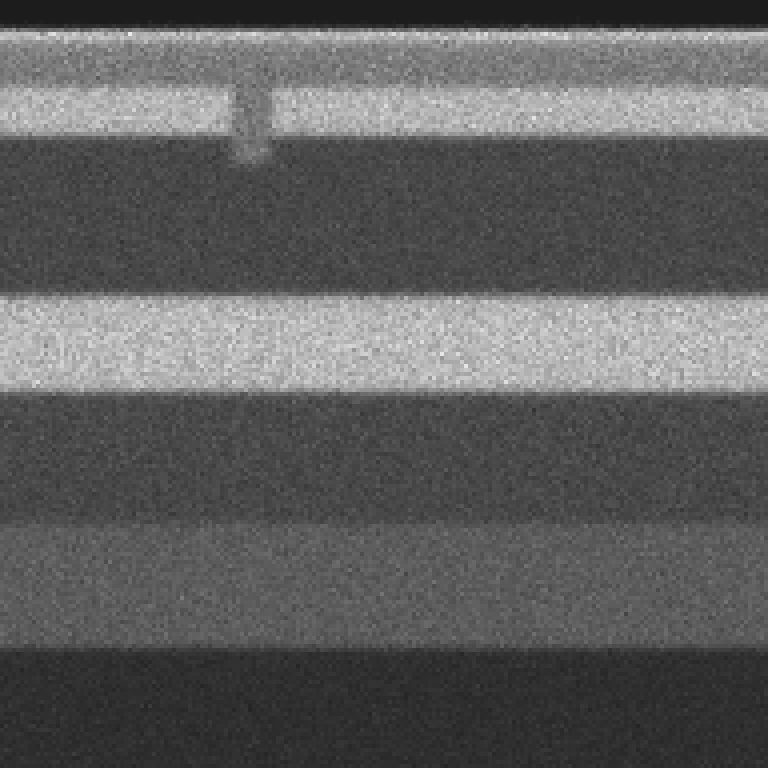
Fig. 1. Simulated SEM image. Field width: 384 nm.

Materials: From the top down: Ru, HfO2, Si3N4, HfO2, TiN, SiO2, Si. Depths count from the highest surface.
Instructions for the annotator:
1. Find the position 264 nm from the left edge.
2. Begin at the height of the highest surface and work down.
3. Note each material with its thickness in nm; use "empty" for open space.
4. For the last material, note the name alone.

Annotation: Ru 28, HfO2 24, Si3N4 80, HfO2 48, TiN 66, SiO2 62, Si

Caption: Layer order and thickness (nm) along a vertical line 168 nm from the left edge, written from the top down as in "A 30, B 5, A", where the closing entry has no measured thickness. Ru 28, HfO2 24, Si3N4 80, HfO2 48, TiN 66, SiO2 62, Si